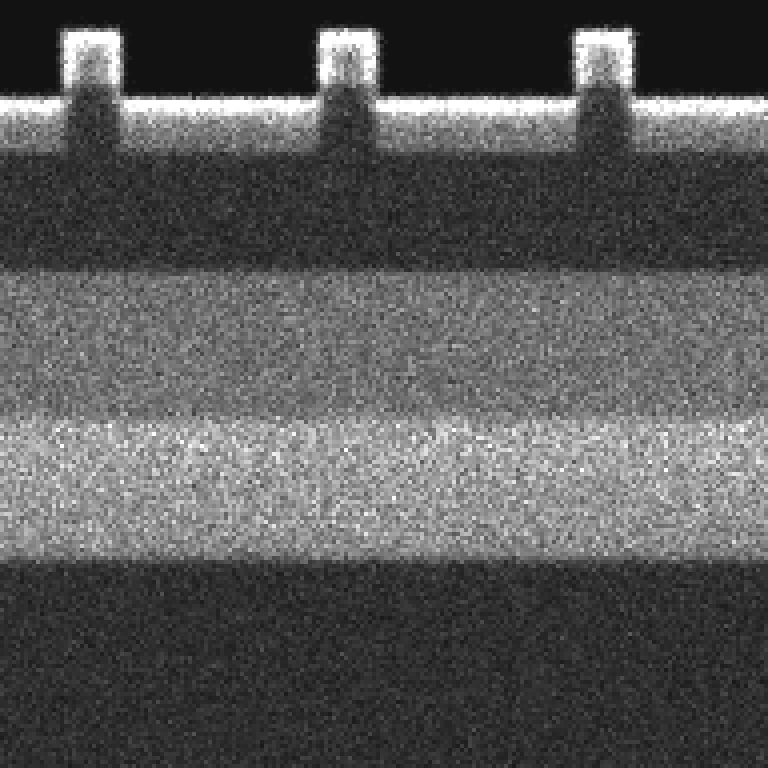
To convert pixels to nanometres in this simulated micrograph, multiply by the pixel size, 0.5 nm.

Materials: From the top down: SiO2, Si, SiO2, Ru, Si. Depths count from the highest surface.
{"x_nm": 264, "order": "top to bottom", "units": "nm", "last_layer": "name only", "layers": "empty 34, SiO2 26, Si 60, SiO2 74, Ru 70, Si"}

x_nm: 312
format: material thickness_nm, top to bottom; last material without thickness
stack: SiO2 26, Si 94, SiO2 74, Ru 70, Si